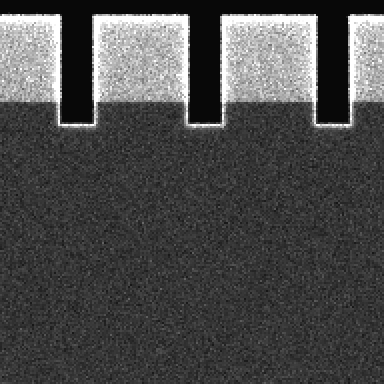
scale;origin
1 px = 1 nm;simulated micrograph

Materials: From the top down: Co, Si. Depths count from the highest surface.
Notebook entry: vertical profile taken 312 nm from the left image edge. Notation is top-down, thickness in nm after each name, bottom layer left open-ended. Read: Co 86, Si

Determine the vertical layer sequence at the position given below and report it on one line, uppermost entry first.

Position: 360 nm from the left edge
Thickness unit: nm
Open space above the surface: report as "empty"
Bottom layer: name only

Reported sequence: Co 86, Si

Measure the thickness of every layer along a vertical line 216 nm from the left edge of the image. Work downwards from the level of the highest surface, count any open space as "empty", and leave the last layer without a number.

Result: empty 108, Si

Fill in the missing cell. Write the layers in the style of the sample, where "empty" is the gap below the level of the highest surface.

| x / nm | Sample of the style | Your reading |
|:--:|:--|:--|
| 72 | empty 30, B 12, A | empty 108, Si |